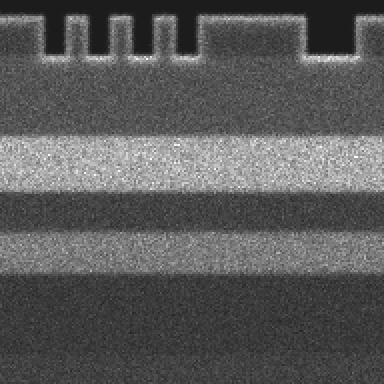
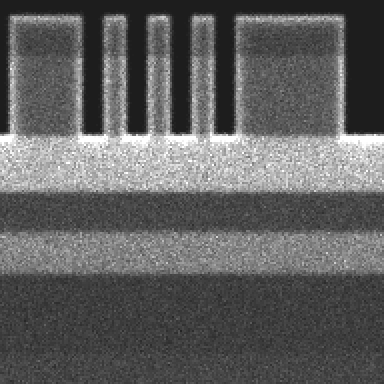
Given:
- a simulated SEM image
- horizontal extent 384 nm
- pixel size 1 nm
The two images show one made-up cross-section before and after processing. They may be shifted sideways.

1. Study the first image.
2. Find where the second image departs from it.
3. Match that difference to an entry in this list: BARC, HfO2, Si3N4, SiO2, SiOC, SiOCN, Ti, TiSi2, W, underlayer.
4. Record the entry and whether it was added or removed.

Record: SiO2 / removed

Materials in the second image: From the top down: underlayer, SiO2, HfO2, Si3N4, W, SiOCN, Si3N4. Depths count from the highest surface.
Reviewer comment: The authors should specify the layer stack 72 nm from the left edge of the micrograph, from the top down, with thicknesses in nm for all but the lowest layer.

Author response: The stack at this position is underlayer 40, SiO2 80, HfO2 56, Si3N4 40, W 42, SiOCN 80, Si3N4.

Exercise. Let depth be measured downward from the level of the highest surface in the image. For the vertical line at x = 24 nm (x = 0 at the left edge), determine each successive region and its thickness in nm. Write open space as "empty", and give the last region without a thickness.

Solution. underlayer 40, SiO2 80, HfO2 56, Si3N4 40, W 42, SiOCN 80, Si3N4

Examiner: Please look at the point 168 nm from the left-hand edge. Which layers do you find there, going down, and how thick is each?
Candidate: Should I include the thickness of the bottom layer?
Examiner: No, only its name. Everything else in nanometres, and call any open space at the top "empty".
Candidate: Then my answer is underlayer 40, SiO2 80, HfO2 56, Si3N4 40, W 42, SiOCN 80, Si3N4